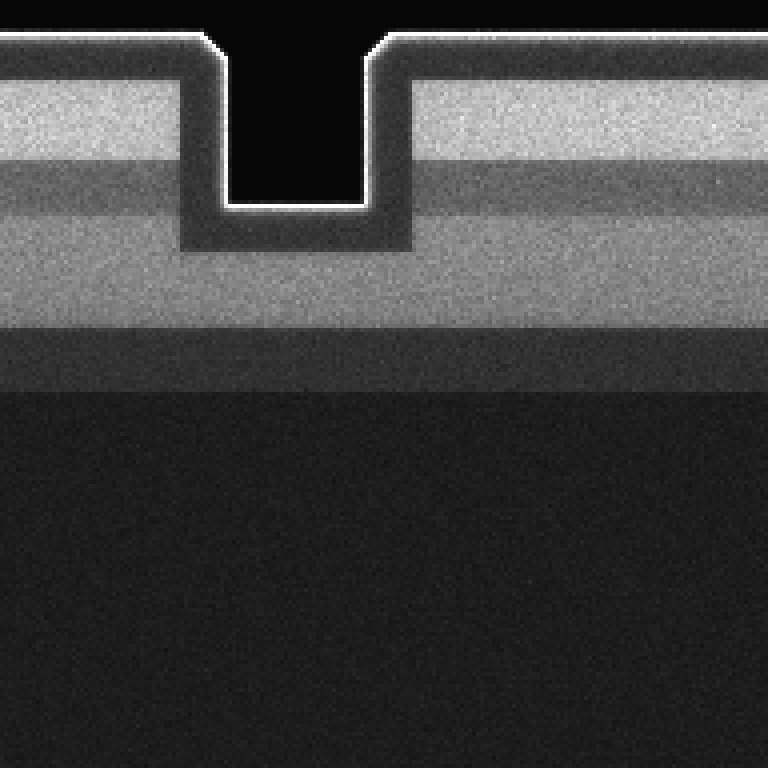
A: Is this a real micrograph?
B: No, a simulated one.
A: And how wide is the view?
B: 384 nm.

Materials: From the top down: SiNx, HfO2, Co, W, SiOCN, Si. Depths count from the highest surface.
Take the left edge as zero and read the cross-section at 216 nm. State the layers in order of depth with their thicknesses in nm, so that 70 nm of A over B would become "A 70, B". SiNx 24, HfO2 40, Co 28, W 56, SiOCN 32, Si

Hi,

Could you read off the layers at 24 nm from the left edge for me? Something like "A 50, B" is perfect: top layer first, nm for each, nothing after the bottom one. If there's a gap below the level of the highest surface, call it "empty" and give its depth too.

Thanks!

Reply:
SiNx 24, HfO2 40, Co 28, W 56, SiOCN 32, Si